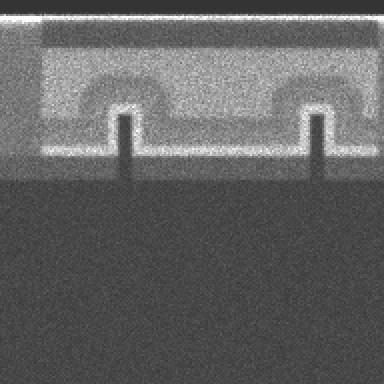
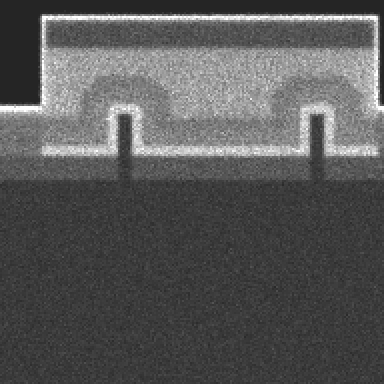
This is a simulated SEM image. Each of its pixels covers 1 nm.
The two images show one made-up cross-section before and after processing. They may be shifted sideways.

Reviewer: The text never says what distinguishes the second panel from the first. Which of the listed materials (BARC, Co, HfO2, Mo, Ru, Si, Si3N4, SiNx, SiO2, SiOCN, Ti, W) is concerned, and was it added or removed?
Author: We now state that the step removed SiO2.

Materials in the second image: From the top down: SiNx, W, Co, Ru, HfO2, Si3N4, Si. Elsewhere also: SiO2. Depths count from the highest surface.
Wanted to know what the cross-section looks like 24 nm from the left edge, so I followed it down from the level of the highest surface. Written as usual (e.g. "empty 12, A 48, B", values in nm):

empty 90, SiO2 50, Si3N4 24, Si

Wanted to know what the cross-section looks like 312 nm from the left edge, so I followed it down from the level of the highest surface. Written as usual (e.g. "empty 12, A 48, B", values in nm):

SiNx 32, W 28, Co 12, Ru 16, HfO2 10, Si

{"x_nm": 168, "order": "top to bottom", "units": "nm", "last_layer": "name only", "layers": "SiNx 32, W 46, Co 36, Ru 16, HfO2 10, Si3N4 24, Si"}